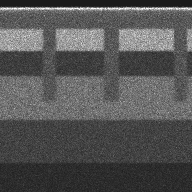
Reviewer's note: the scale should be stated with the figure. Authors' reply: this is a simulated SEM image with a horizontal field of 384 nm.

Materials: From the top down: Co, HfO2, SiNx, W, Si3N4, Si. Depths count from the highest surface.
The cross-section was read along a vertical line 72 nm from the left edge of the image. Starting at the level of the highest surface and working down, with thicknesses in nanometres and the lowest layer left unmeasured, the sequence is Co 42, HfO2 44, SiNx 50, W 88, Si3N4 86, Si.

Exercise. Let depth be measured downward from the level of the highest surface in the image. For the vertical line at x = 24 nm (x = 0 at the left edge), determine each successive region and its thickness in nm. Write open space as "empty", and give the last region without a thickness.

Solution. Co 42, HfO2 44, SiNx 50, W 88, Si3N4 86, Si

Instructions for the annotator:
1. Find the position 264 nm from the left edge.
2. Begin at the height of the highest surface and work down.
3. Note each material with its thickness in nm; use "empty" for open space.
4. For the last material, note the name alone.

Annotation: Co 42, HfO2 44, SiNx 50, W 88, Si3N4 86, Si